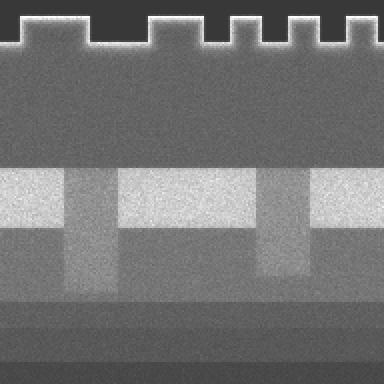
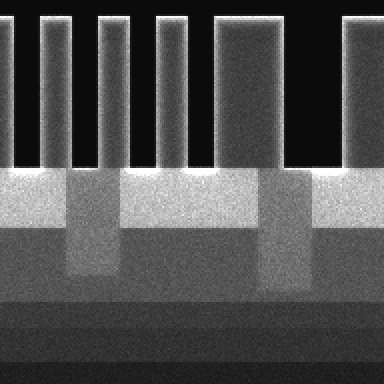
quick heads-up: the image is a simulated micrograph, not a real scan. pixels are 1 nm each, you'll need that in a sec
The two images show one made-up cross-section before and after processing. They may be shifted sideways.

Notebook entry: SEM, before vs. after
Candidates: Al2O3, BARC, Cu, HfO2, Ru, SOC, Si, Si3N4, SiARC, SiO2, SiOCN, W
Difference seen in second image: SOC removed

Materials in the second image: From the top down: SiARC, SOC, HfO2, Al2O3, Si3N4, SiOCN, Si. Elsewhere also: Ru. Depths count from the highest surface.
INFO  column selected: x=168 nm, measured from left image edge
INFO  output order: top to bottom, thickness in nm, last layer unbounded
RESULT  SiARC 26, SOC 126, HfO2 60, Al2O3 74, Si3N4 26, SiOCN 34, Si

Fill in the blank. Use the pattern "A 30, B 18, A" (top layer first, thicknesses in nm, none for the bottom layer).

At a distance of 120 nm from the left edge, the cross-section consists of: SiARC 26, SOC 126, HfO2 60, Al2O3 74, Si3N4 26, SiOCN 34, Si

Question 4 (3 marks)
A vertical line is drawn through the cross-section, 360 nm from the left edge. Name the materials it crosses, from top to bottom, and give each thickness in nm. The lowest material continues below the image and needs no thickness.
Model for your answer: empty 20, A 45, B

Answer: SiARC 26, SOC 126, HfO2 60, Al2O3 74, Si3N4 26, SiOCN 34, Si